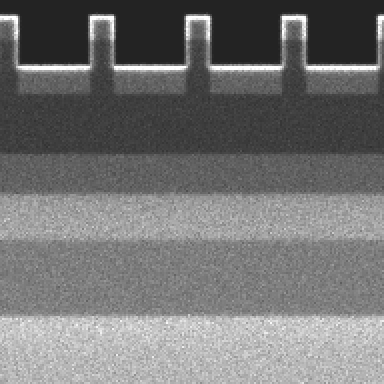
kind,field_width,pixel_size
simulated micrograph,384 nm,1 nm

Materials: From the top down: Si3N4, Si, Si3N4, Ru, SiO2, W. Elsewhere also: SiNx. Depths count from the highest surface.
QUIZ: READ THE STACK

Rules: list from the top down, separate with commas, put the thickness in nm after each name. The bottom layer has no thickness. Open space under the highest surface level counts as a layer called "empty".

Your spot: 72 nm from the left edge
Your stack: empty 50, Si3N4 28, Si 60, Si3N4 40, Ru 46, SiO2 76, W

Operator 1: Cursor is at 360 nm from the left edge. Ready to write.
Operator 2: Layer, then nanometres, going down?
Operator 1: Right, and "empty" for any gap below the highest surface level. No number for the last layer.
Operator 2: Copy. empty 50, Si3N4 28, Si 60, Si3N4 40, Ru 46, SiO2 76, W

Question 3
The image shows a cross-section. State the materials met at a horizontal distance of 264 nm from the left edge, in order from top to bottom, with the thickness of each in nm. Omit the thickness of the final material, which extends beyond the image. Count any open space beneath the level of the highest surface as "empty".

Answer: empty 50, Si3N4 28, Si 60, Si3N4 40, Ru 46, SiO2 76, W